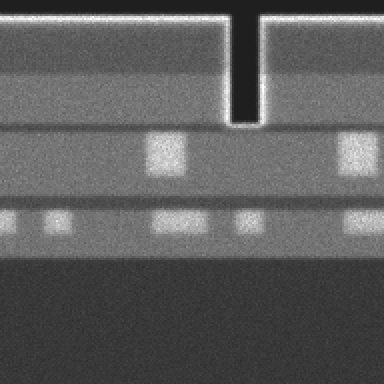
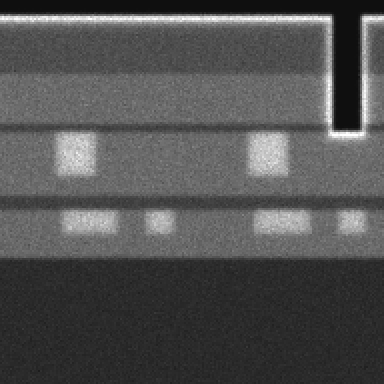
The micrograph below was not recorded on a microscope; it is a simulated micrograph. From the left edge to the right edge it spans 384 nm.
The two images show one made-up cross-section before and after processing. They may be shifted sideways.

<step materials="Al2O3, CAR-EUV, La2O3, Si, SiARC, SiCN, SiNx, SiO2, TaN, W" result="removed SiCN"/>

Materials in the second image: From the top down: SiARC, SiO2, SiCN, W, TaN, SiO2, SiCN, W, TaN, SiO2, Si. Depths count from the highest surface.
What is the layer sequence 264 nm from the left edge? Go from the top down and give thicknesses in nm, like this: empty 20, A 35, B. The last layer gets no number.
SiARC 58, SiO2 50, SiCN 8, W 38, TaN 6, SiO2 20, SiCN 14, W 18, TaN 6, SiO2 24, Si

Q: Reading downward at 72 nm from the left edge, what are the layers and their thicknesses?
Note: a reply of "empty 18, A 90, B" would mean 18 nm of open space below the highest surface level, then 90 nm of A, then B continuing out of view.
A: SiARC 58, SiO2 50, SiCN 8, W 38, TaN 6, SiO2 20, SiCN 14, W 18, TaN 6, SiO2 24, Si